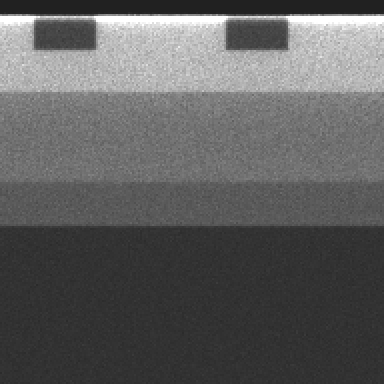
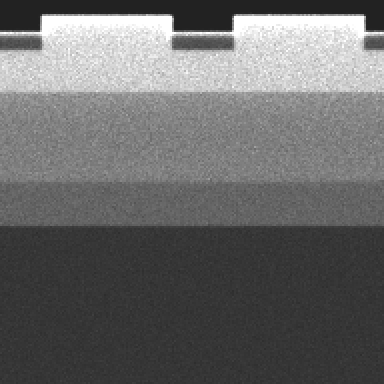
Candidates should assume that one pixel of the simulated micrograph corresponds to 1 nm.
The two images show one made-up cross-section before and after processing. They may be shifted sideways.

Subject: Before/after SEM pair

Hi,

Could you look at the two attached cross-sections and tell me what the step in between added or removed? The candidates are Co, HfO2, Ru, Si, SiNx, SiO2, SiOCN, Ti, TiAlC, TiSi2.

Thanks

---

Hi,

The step removed SiNx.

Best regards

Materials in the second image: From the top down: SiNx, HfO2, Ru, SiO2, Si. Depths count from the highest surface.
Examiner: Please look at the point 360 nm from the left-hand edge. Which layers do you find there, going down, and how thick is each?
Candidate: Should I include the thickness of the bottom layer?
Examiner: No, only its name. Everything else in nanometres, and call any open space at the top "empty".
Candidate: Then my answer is HfO2 76, Ru 90, SiO2 44, Si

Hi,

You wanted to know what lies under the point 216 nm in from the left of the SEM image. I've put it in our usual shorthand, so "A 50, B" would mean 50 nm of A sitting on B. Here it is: empty 16, SiNx 18, HfO2 42, Ru 90, SiO2 44, Si